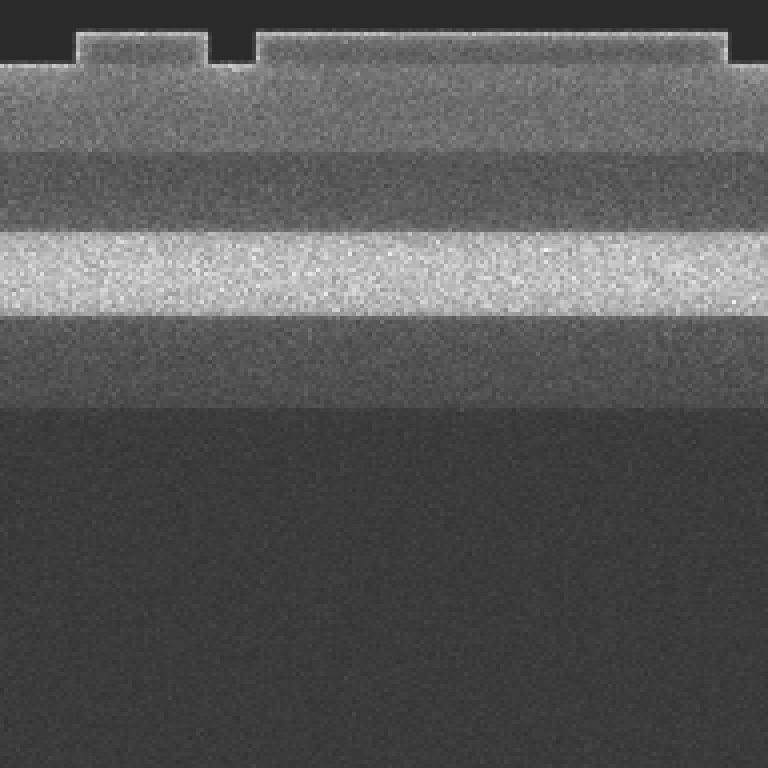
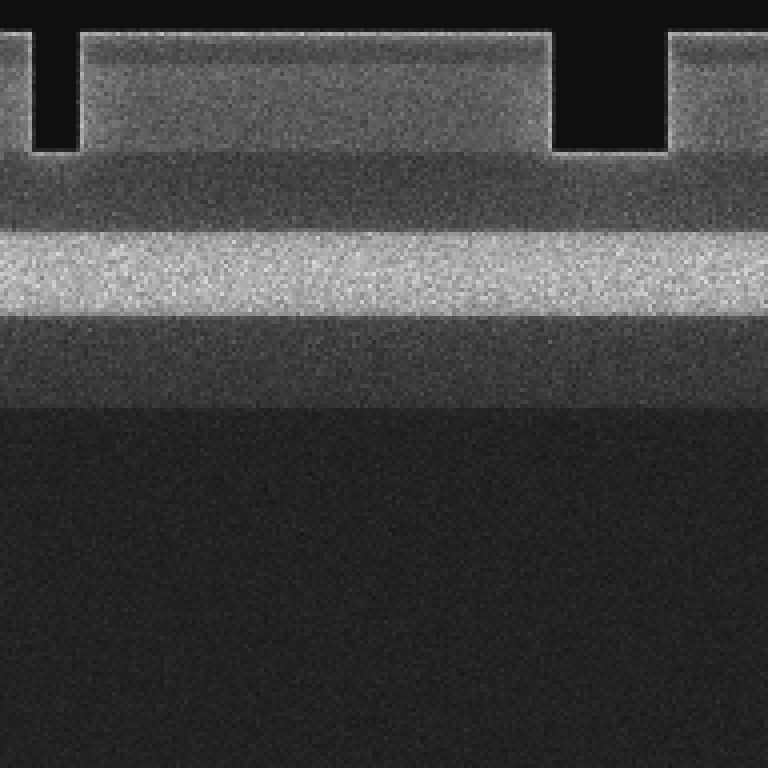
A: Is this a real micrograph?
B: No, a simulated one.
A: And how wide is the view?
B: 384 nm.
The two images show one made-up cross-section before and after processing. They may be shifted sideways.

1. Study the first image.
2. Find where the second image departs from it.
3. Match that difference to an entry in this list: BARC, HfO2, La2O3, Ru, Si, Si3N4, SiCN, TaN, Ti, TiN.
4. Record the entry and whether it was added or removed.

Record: Ru / removed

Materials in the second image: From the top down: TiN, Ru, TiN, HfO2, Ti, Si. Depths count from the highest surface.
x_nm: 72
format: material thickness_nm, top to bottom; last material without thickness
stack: TiN 16, Ru 44, TiN 40, HfO2 42, Ti 46, Si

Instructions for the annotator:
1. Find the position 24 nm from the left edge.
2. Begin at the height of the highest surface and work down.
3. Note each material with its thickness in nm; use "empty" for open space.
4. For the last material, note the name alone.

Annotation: empty 60, TiN 40, HfO2 42, Ti 46, Si